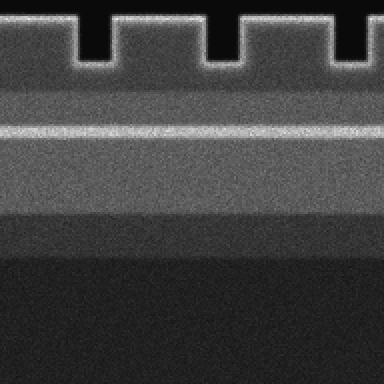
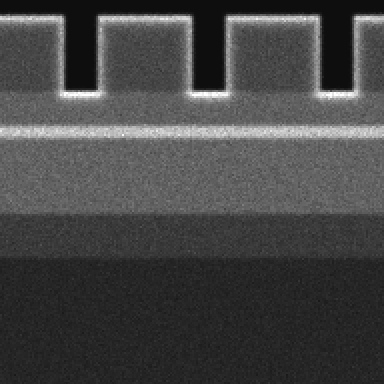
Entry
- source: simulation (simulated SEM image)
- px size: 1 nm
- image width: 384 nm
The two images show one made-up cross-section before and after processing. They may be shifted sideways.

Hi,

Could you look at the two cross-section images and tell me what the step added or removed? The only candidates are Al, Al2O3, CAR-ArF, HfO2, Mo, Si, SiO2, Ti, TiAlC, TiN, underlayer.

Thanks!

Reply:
removed underlayer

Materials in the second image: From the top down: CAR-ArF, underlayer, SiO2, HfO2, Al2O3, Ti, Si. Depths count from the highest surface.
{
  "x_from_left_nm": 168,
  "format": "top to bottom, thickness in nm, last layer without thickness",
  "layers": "CAR-ArF 46, underlayer 30, SiO2 34, HfO2 12, Al2O3 76, Ti 44, Si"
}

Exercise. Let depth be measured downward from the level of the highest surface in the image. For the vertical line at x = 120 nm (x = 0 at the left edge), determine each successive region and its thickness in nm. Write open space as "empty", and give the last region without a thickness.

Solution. CAR-ArF 46, underlayer 30, SiO2 34, HfO2 12, Al2O3 76, Ti 44, Si